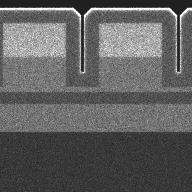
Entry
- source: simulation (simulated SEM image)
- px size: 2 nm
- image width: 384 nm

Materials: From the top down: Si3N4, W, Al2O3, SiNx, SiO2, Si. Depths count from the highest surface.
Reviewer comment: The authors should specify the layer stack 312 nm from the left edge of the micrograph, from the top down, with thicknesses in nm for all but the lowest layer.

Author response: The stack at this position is Si3N4 30, W 68, Al2O3 70, SiNx 24, SiO2 56, Si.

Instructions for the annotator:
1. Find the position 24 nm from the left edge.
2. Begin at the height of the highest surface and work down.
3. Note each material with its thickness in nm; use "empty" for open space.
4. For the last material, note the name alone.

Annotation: Si3N4 30, W 68, Al2O3 70, SiNx 24, SiO2 56, Si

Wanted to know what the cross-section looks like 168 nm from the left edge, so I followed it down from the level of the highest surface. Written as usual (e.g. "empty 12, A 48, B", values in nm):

empty 14, Si3N4 144, Al2O3 10, SiNx 24, SiO2 56, Si